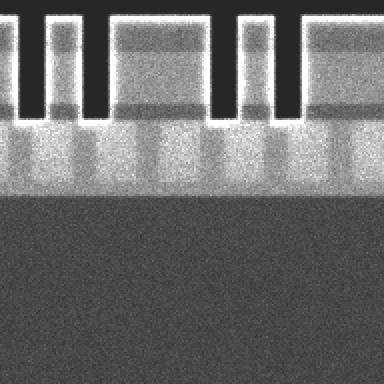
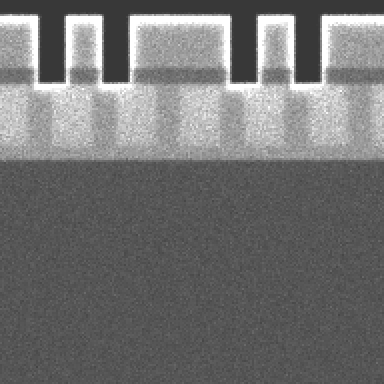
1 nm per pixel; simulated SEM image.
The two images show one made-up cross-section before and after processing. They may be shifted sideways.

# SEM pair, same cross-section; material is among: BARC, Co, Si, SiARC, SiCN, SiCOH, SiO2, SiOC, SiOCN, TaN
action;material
removed;SiARC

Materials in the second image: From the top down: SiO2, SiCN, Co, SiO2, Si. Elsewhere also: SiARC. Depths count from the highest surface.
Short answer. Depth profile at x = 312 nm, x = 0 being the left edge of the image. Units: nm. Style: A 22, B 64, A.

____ empty 68, Co 62, SiO2 14, Si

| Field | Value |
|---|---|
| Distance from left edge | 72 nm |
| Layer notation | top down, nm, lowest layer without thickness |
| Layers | SiO2 52, SiCN 16, Co 62, SiO2 14, Si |